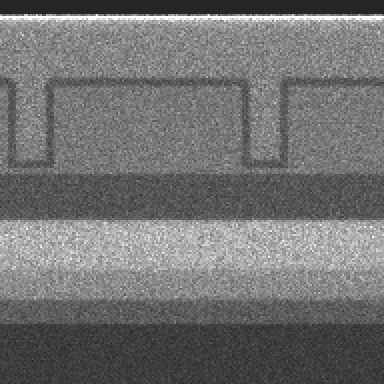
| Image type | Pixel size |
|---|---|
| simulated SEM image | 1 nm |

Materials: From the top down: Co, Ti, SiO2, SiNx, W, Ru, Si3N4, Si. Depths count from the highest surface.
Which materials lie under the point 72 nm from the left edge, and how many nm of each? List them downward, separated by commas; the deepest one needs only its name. Co 62, Ti 8, SiO2 88, SiNx 46, W 50, Ru 30, Si3N4 24, Si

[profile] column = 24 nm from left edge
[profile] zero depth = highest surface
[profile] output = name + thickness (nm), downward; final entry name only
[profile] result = Co 144, Ti 8, SiO2 6, SiNx 46, W 50, Ru 30, Si3N4 24, Si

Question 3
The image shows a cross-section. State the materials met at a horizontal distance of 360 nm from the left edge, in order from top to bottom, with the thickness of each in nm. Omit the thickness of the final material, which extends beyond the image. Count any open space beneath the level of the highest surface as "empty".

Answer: Co 62, Ti 8, SiO2 88, SiNx 46, W 50, Ru 30, Si3N4 24, Si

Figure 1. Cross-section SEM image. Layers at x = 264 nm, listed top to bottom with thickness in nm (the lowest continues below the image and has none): Co 144, Ti 8, SiO2 6, SiNx 46, W 50, Ru 30, Si3N4 24, Si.